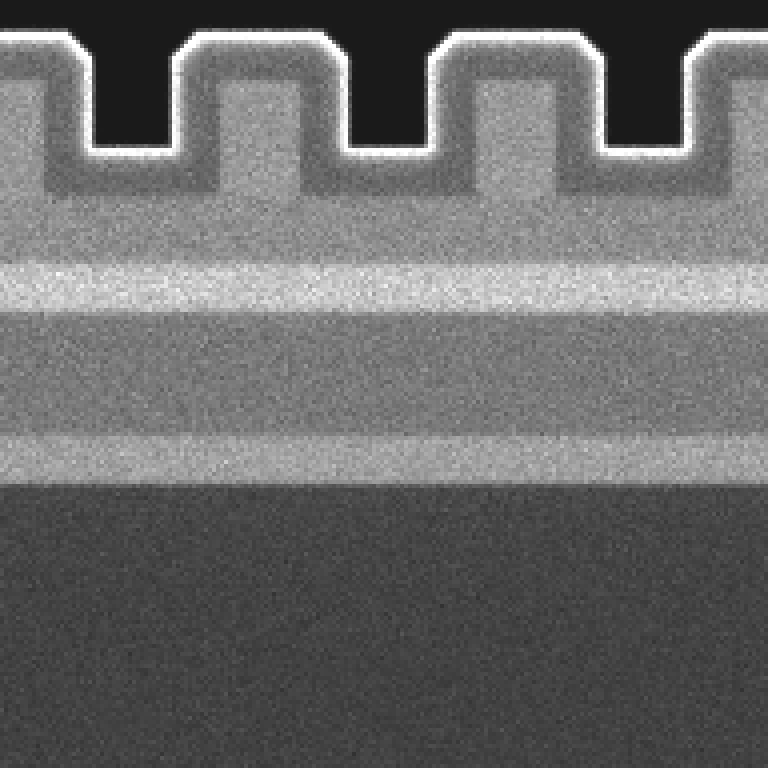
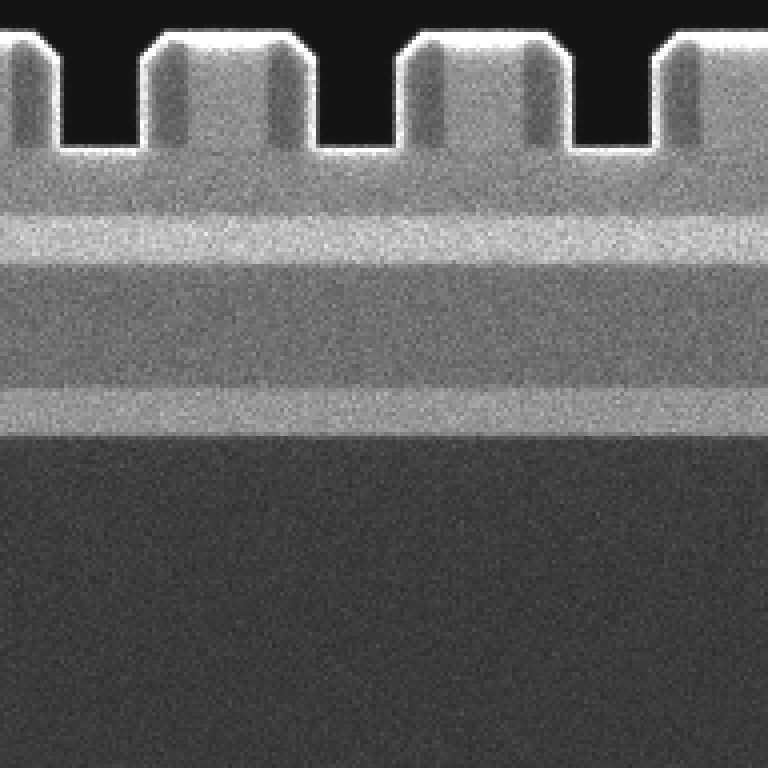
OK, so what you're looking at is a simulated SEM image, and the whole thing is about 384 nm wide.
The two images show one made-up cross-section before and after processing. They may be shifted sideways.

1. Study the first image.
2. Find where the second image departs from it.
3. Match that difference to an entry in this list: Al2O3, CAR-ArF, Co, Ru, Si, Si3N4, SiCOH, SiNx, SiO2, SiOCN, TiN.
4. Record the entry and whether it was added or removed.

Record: SiOCN / removed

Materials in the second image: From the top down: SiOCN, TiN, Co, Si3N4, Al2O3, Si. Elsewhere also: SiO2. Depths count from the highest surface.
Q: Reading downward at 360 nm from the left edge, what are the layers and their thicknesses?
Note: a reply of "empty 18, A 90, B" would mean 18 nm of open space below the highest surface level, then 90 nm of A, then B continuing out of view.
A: SiO2 58, TiN 34, Co 24, Si3N4 62, Al2O3 24, Si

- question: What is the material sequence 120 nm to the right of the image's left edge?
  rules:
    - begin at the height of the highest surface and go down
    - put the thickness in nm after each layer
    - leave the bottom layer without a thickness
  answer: SiO2 58, TiN 34, Co 24, Si3N4 62, Al2O3 24, Si